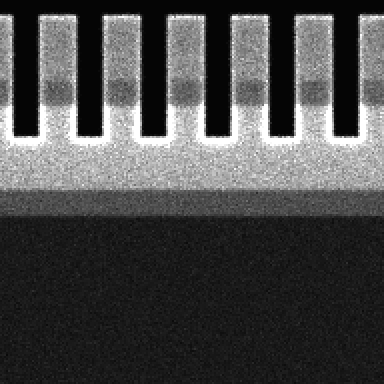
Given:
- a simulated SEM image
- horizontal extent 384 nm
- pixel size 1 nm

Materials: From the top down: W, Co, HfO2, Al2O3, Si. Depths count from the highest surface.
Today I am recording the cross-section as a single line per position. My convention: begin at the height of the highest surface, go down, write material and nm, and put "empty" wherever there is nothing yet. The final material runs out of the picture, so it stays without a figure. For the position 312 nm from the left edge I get W 64, Co 26, HfO2 84, Al2O3 26, Si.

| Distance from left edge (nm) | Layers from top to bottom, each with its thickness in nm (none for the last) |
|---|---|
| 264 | W 64, Co 26, HfO2 84, Al2O3 26, Si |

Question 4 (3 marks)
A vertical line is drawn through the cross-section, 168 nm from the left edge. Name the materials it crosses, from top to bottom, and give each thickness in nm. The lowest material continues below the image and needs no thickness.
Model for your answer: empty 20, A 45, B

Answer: W 64, Co 26, HfO2 84, Al2O3 26, Si